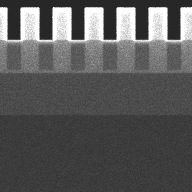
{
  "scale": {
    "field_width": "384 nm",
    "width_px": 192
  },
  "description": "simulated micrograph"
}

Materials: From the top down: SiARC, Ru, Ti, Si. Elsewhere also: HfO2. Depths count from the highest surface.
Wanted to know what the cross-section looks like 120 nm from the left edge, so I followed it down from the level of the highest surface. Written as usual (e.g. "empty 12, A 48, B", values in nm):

HfO2 64, Ru 66, Ti 84, Si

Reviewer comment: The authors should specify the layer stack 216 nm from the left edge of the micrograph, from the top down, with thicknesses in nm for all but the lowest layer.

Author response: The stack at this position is empty 64, SiARC 60, Ru 6, Ti 84, Si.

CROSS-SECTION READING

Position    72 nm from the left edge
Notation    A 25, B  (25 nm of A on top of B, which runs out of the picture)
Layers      HfO2 64, Ru 66, Ti 84, Si